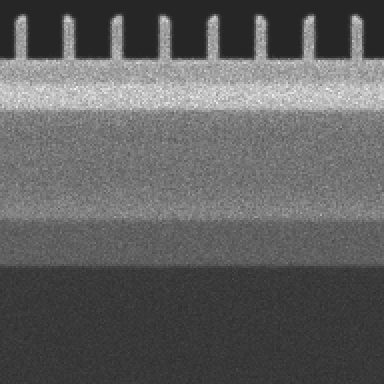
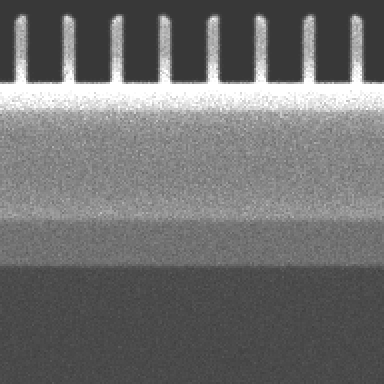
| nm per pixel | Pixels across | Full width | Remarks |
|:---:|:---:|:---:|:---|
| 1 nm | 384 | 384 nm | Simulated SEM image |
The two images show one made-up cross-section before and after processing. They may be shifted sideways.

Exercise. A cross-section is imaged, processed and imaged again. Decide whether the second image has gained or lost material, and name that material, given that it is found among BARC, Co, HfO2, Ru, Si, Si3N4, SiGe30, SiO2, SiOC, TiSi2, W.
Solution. removed: W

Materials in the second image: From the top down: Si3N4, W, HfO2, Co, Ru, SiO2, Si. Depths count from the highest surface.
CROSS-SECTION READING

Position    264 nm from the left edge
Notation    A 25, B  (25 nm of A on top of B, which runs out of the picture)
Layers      empty 4, Si3N4 40, W 24, HfO2 26, Co 34, Ru 76, SiO2 46, Si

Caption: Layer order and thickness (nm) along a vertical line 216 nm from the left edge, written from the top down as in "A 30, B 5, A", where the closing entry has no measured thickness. Si3N4 44, W 24, HfO2 26, Co 34, Ru 76, SiO2 46, Si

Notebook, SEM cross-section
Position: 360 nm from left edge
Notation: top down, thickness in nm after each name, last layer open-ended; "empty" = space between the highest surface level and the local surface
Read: empty 4, Si3N4 40, W 24, HfO2 26, Co 34, Ru 76, SiO2 46, Si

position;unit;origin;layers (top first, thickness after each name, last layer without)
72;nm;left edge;empty 4, Si3N4 40, W 24, HfO2 26, Co 34, Ru 76, SiO2 46, Si